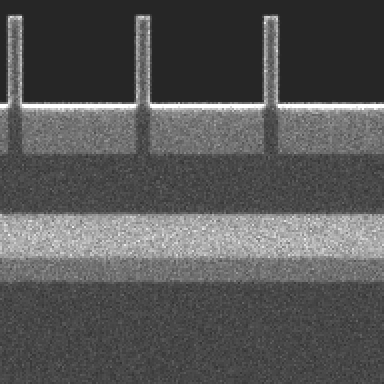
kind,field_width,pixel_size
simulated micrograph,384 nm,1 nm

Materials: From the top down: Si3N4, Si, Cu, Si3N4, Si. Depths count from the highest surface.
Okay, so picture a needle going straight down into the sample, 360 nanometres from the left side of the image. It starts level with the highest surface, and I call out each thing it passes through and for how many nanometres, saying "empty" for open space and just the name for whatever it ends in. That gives empty 88, Si3N4 50, Si 60, Cu 44, Si3N4 24, Si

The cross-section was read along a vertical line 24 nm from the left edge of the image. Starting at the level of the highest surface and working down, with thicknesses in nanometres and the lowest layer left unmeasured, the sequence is empty 88, Si3N4 50, Si 60, Cu 44, Si3N4 24, Si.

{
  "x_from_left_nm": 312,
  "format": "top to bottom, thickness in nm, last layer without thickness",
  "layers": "empty 88, Si3N4 50, Si 60, Cu 44, Si3N4 24, Si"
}